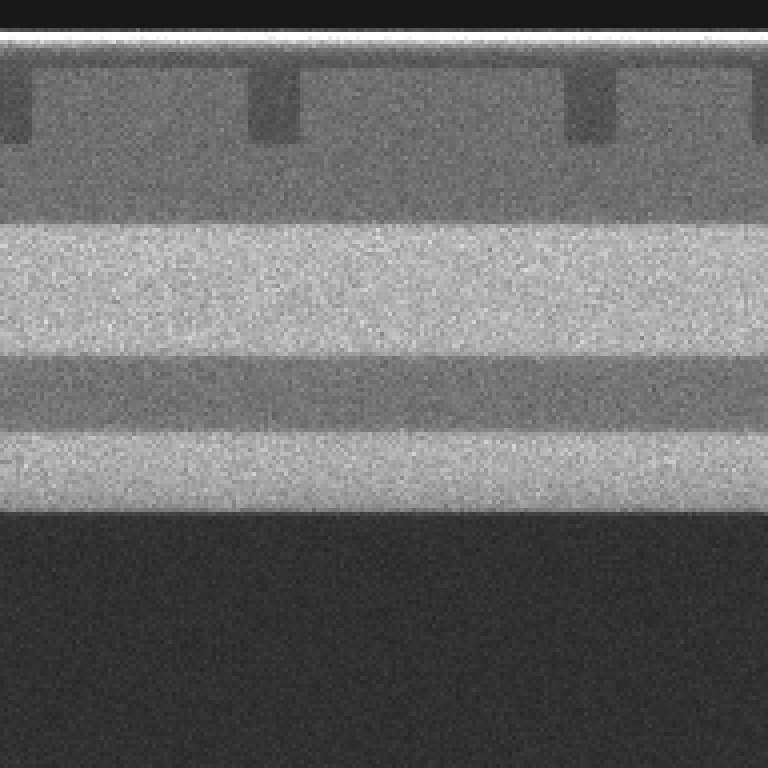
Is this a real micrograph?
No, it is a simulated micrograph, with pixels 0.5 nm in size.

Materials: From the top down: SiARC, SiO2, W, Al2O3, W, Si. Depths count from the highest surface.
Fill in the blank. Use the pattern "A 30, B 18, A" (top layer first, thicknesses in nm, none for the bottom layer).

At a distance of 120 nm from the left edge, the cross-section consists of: SiARC 18, SiO2 78, W 66, Al2O3 38, W 40, Si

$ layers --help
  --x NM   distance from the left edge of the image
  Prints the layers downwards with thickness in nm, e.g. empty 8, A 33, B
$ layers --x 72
SiARC 18, SiO2 78, W 66, Al2O3 38, W 40, Si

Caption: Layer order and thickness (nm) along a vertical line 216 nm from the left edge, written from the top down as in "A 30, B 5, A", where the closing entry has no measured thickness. SiARC 18, SiO2 78, W 66, Al2O3 38, W 40, Si